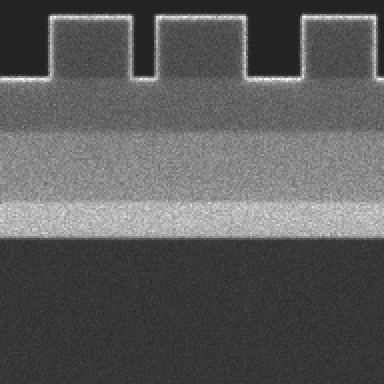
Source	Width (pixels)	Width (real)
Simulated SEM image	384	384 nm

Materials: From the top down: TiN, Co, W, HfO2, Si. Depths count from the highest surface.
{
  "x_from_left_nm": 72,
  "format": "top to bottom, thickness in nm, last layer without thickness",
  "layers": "TiN 62, Co 54, W 70, HfO2 36, Si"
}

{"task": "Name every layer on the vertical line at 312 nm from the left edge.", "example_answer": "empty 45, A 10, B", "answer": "TiN 62, Co 54, W 70, HfO2 36, Si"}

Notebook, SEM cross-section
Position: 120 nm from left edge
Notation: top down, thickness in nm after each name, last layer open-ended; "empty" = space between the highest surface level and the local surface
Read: TiN 62, Co 54, W 70, HfO2 36, Si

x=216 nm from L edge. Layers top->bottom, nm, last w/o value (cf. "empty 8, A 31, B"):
TiN 62, Co 54, W 70, HfO2 36, Si